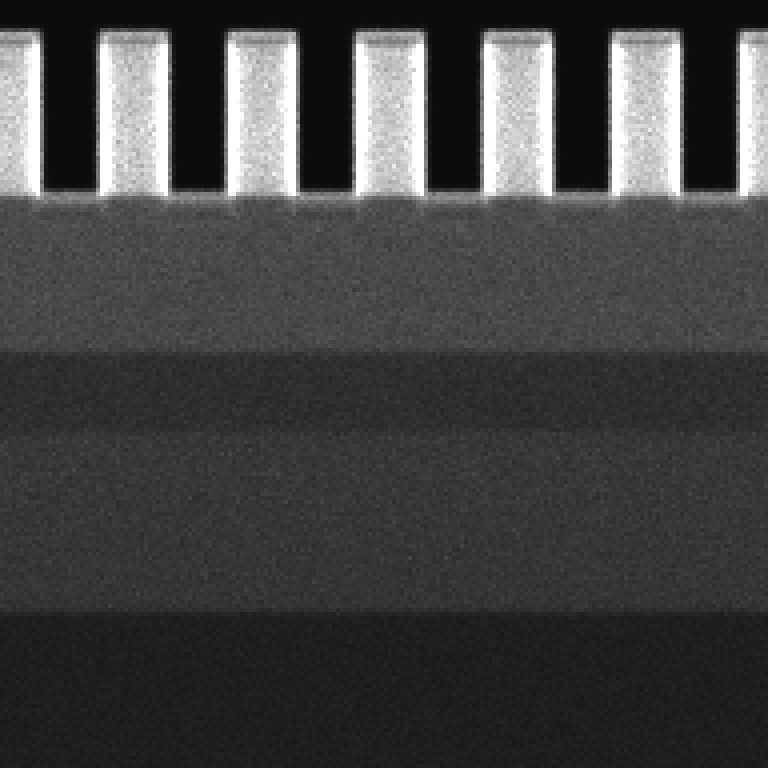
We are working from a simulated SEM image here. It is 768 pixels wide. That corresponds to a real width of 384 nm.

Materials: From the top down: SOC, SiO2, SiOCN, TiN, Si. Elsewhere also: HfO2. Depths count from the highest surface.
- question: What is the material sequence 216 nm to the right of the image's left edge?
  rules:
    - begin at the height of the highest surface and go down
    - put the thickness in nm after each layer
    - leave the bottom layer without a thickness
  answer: empty 80, SOC 14, SiO2 66, SiOCN 40, TiN 90, Si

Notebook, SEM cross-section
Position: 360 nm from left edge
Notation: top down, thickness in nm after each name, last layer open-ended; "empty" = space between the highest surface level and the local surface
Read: empty 80, SOC 14, SiO2 66, SiOCN 40, TiN 90, Si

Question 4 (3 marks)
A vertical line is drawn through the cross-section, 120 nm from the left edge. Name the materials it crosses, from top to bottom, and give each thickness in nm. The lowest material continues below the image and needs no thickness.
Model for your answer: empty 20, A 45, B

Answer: HfO2 82, SiO2 78, SiOCN 40, TiN 90, Si